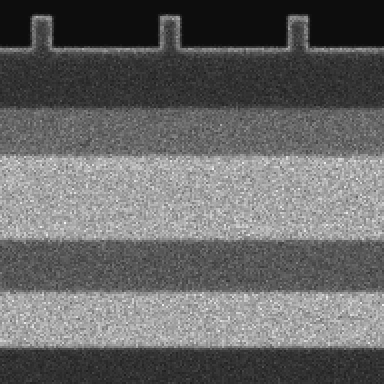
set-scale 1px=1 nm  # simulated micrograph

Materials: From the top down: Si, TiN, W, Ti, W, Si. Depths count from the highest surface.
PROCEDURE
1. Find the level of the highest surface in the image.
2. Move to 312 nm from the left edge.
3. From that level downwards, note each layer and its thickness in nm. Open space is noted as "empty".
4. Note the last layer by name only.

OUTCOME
empty 32, Si 60, TiN 48, W 84, Ti 52, W 56, Si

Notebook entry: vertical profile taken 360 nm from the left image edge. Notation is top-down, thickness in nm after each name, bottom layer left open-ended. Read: empty 32, Si 60, TiN 48, W 84, Ti 52, W 56, Si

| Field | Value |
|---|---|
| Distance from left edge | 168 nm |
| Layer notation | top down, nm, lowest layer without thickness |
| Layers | Si 92, TiN 48, W 84, Ti 52, W 56, Si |